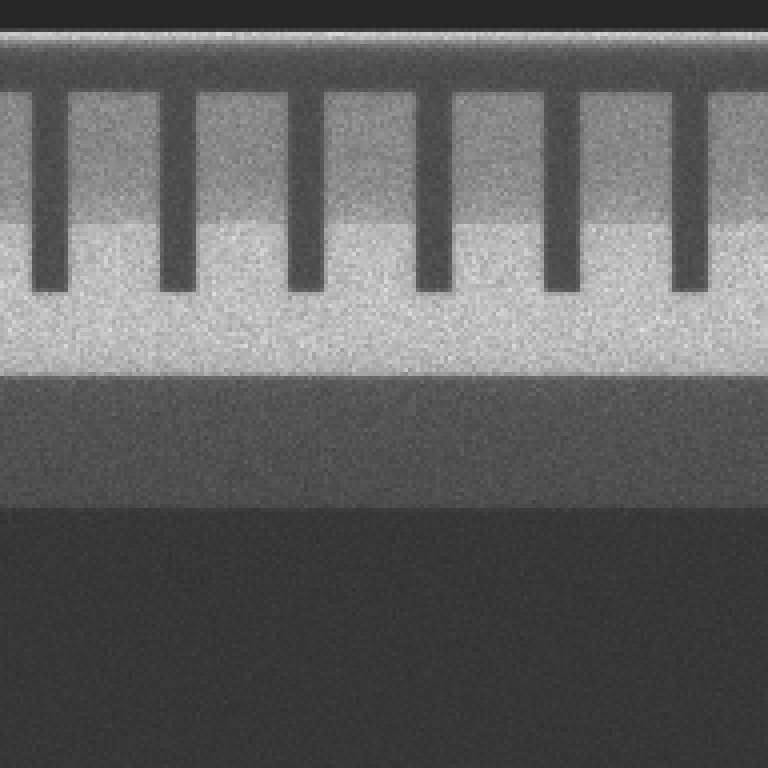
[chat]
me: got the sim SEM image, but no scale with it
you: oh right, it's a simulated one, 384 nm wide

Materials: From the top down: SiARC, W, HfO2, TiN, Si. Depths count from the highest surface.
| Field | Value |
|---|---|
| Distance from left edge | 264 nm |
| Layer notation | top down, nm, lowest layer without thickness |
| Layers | SiARC 30, W 66, HfO2 76, TiN 66, Si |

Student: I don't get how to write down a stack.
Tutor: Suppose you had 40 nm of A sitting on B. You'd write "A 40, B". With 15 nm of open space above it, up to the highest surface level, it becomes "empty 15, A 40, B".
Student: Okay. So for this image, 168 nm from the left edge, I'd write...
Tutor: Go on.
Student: SiARC 30, W 66, HfO2 76, TiN 66, Si